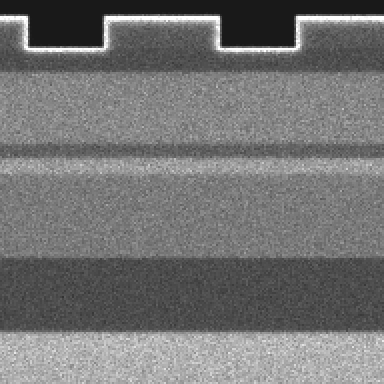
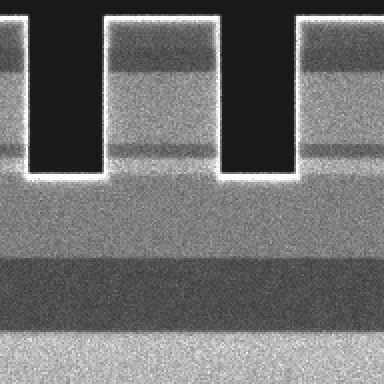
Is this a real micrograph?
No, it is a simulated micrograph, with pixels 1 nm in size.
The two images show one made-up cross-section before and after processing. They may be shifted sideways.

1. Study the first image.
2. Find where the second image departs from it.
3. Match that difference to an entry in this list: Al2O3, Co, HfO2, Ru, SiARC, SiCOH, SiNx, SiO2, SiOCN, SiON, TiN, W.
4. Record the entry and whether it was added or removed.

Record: Co and Ru and SiNx and TiN / removed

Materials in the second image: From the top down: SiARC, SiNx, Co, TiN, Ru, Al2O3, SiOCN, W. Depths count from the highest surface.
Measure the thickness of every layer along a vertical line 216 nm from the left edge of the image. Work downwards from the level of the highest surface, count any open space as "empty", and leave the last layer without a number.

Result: SiARC 32, SiNx 24, Co 72, TiN 14, Ru 16, Al2O3 84, SiOCN 74, W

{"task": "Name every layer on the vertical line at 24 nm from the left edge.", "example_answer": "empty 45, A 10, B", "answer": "SiARC 32, SiNx 24, Co 72, TiN 14, Ru 16, Al2O3 84, SiOCN 74, W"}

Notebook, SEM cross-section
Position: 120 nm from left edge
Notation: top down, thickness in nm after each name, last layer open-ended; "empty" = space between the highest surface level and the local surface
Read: SiARC 32, SiNx 24, Co 72, TiN 14, Ru 16, Al2O3 84, SiOCN 74, W